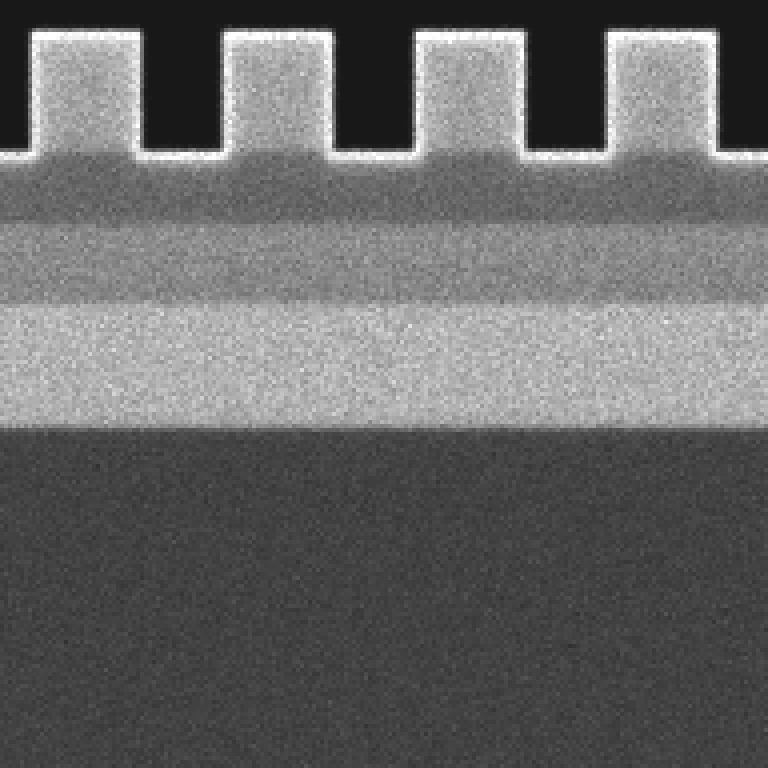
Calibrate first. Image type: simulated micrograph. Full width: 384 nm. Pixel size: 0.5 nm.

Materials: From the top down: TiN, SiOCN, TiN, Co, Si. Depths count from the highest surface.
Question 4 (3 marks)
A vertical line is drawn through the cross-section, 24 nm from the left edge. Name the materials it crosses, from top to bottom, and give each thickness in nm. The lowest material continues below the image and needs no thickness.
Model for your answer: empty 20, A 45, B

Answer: TiN 60, SiOCN 36, TiN 40, Co 62, Si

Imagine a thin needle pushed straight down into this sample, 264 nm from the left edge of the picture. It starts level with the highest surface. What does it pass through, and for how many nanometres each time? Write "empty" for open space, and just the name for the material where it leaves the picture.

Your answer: empty 60, SiOCN 36, TiN 40, Co 62, Si